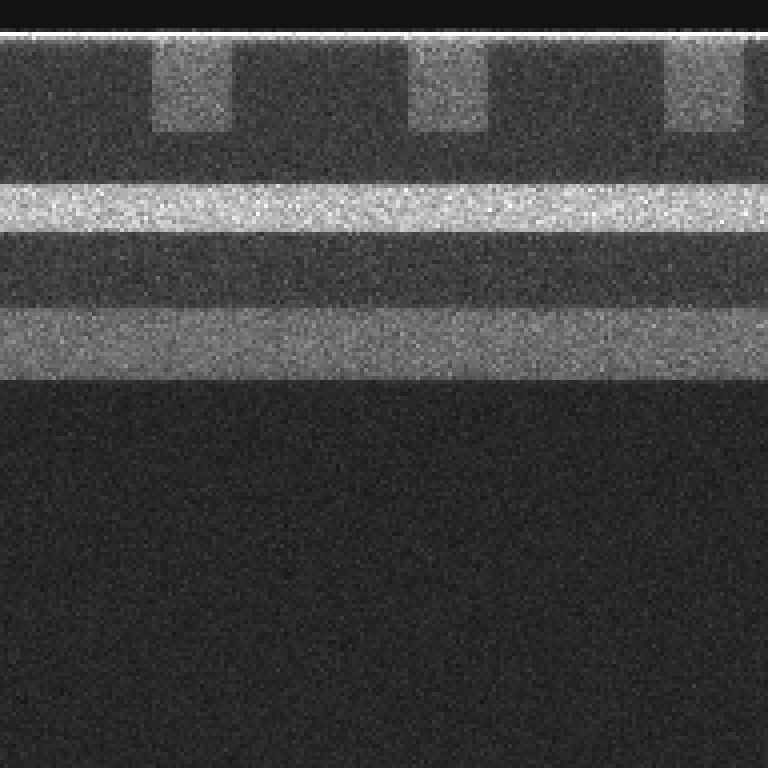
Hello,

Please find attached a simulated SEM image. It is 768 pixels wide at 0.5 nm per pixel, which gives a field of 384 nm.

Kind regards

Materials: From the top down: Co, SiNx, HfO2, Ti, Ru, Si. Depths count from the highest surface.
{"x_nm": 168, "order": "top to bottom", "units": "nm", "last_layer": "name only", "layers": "SiNx 76, HfO2 24, Ti 38, Ru 36, Si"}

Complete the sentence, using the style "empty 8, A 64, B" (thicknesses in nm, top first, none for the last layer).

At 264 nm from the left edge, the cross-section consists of SiNx 76, HfO2 24, Ti 38, Ru 36, Si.